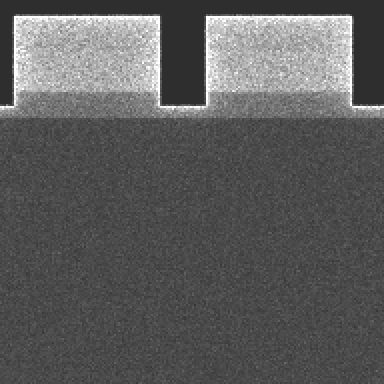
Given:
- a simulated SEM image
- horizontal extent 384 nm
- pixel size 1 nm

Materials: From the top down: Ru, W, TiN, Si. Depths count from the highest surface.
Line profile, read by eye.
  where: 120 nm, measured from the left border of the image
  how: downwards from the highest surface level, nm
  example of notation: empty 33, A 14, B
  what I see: Ru 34, W 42, TiN 26, Si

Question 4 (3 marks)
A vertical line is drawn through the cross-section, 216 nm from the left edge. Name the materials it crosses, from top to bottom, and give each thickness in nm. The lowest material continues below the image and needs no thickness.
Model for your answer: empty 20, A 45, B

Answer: Ru 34, W 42, TiN 26, Si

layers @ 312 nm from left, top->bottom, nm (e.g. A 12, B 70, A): Ru 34, W 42, TiN 26, Si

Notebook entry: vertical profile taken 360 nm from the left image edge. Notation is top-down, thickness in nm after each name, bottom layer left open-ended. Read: empty 90, TiN 12, Si